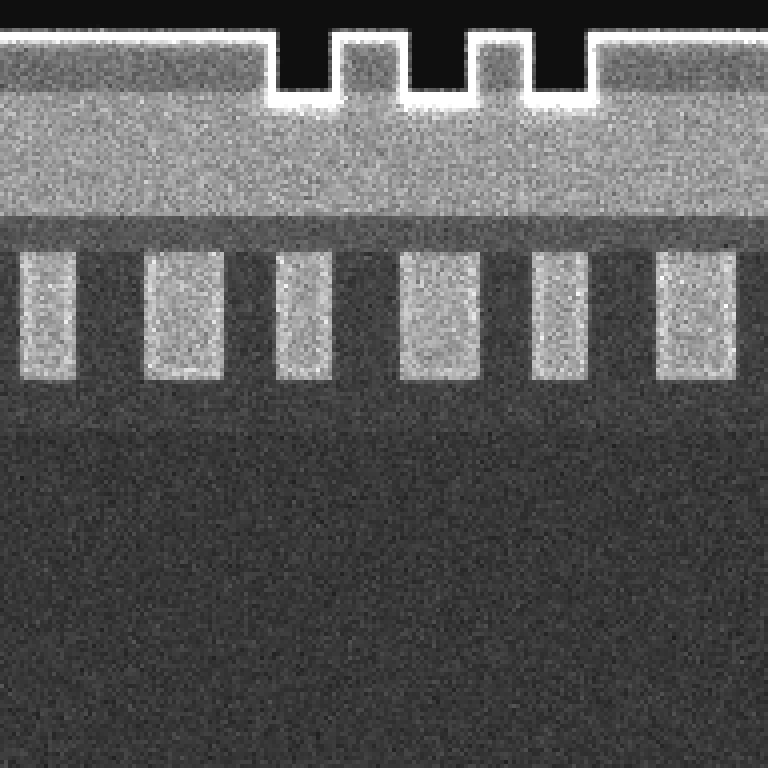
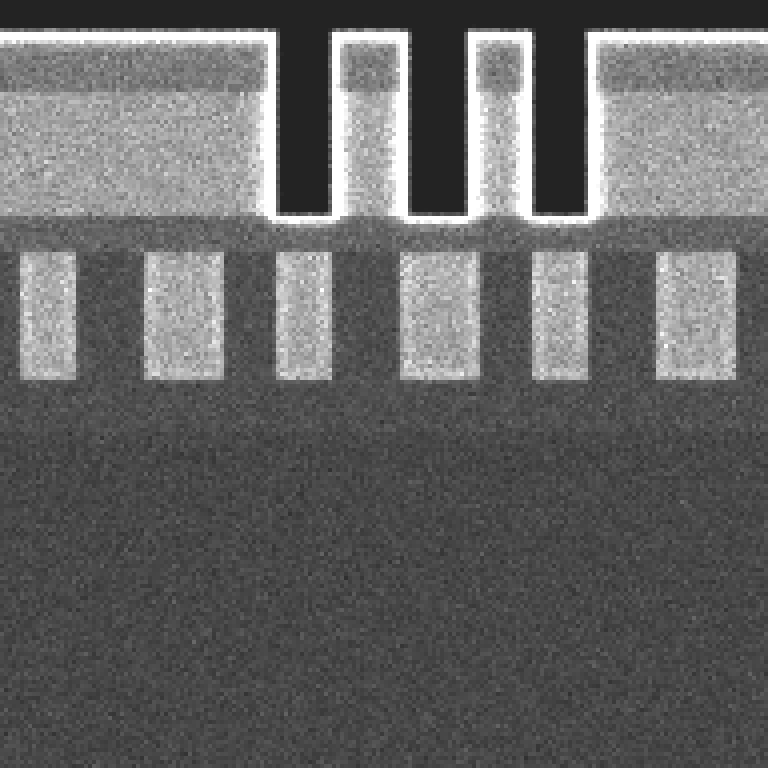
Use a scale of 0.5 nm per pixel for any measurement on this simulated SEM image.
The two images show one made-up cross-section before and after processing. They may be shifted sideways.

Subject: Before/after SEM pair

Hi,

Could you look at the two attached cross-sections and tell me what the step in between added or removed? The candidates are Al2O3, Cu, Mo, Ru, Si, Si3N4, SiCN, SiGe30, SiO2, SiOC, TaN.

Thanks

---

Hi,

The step removed SiO2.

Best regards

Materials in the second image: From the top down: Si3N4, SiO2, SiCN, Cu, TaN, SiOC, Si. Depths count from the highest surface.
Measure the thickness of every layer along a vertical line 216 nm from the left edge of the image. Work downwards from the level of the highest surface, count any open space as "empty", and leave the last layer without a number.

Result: empty 92, SiCN 18, Cu 58, TaN 6, SiOC 26, Si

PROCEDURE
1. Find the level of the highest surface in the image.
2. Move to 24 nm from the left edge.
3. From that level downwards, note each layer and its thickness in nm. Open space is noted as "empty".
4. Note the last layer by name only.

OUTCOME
Si3N4 30, SiO2 62, SiCN 18, Cu 58, TaN 6, SiOC 26, Si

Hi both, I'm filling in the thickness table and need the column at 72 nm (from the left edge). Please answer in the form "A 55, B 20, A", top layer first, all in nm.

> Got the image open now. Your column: Si3N4 30, SiO2 62, SiCN 18, TaN 64, SiOC 26, Si